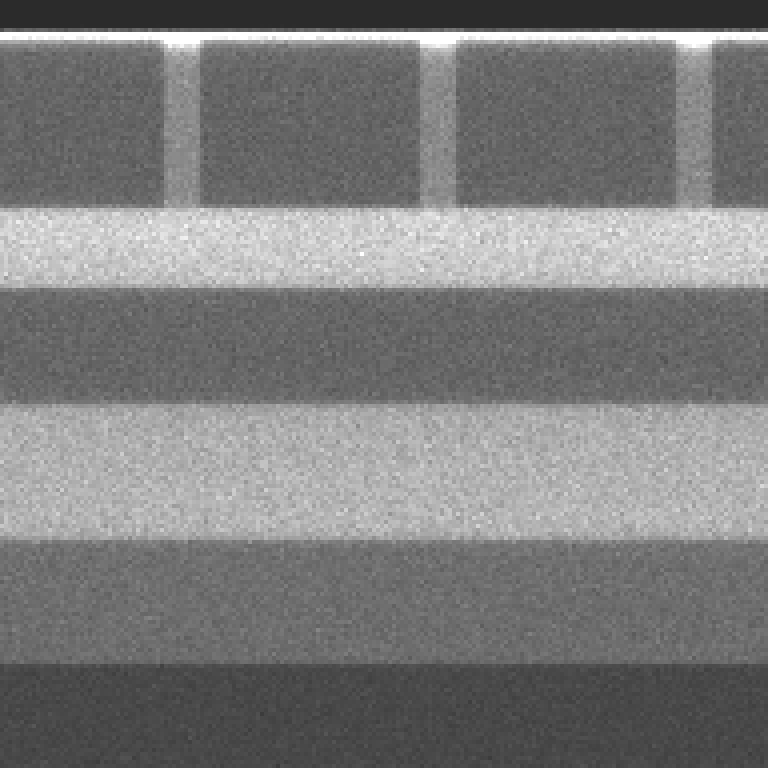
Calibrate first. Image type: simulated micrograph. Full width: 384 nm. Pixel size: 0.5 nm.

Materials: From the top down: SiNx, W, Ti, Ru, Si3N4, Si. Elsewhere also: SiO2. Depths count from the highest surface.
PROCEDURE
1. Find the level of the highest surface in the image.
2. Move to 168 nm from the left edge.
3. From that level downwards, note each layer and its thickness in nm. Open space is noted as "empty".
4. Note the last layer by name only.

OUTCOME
SiNx 88, W 40, Ti 58, Ru 68, Si3N4 62, Si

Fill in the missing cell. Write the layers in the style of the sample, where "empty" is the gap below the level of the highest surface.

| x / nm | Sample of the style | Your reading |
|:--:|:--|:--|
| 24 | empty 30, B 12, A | SiNx 88, W 40, Ti 58, Ru 68, Si3N4 62, Si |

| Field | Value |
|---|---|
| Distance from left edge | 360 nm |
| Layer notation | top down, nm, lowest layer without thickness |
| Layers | SiNx 88, W 40, Ti 58, Ru 68, Si3N4 62, Si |